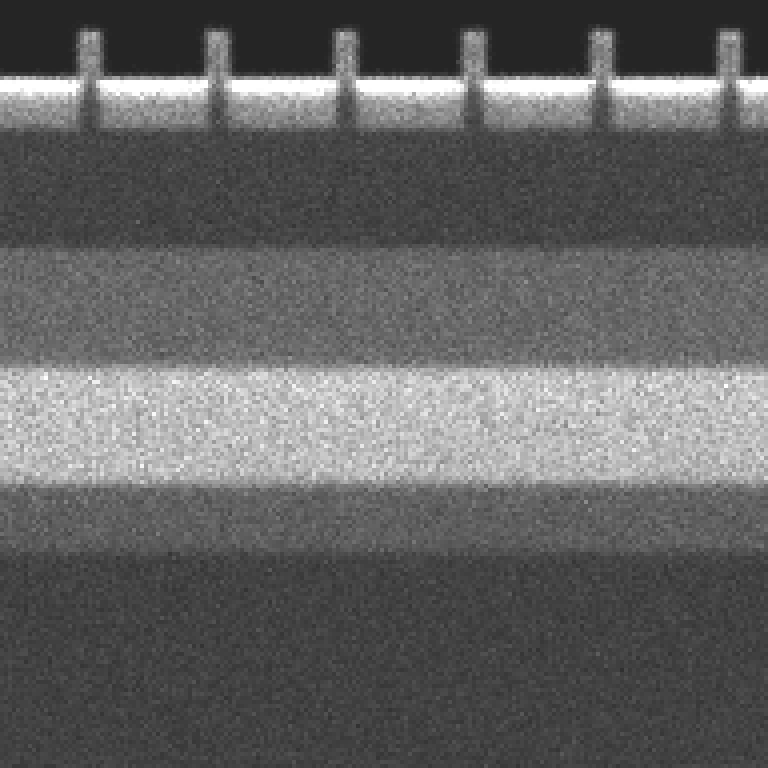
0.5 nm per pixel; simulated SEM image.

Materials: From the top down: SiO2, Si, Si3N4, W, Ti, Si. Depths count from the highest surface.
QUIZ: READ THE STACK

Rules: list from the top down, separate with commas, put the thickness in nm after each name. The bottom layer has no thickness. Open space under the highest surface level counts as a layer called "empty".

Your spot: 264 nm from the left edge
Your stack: empty 24, SiO2 24, Si 60, Si3N4 60, W 58, Ti 34, Si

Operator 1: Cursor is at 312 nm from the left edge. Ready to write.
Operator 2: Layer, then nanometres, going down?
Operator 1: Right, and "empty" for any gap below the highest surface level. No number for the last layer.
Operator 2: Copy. empty 24, SiO2 24, Si 60, Si3N4 60, W 58, Ti 34, Si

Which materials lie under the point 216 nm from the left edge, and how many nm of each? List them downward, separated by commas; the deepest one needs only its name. empty 24, SiO2 24, Si 60, Si3N4 60, W 58, Ti 34, Si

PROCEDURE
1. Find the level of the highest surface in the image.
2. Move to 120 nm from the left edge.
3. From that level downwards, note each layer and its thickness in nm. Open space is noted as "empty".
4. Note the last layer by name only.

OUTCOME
empty 24, SiO2 24, Si 60, Si3N4 60, W 58, Ti 34, Si